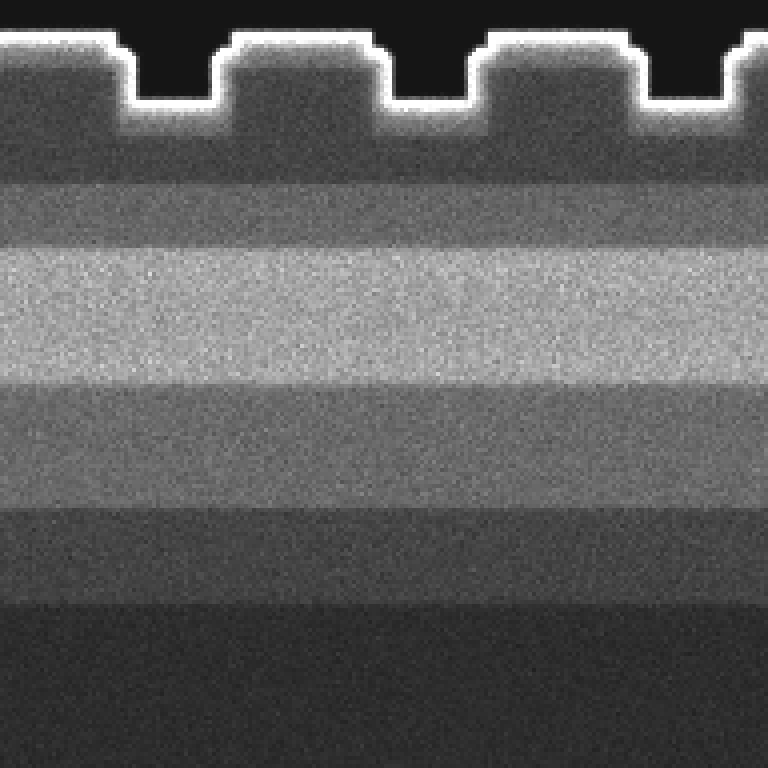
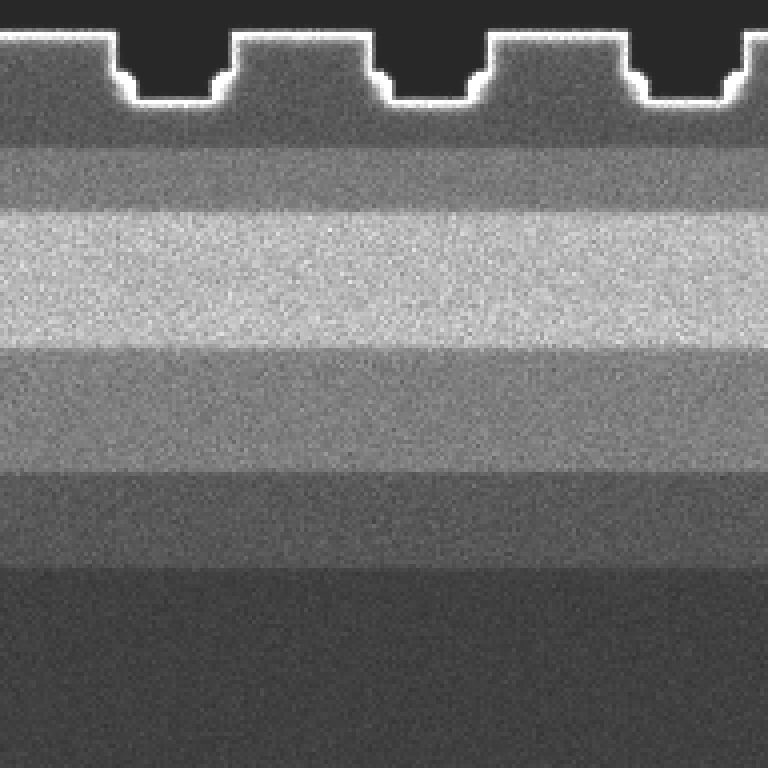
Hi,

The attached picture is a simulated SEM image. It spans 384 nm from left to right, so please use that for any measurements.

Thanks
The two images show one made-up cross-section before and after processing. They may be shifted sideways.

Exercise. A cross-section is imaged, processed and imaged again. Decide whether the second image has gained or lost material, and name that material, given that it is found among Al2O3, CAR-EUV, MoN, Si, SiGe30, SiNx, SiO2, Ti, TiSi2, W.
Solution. removed: SiO2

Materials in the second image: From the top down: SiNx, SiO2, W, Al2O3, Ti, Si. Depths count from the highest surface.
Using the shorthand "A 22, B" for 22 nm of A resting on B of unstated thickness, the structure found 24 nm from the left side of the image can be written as SiNx 58, SiO2 32, W 68, Al2O3 62, Ti 48, Si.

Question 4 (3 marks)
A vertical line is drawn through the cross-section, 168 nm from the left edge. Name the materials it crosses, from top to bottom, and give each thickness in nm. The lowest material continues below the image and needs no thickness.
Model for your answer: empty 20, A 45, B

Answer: SiNx 58, SiO2 32, W 68, Al2O3 62, Ti 48, Si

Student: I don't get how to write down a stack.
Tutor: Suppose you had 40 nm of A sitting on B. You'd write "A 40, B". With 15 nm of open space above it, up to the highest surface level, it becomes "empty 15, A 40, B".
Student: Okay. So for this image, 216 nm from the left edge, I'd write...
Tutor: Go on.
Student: empty 34, SiNx 24, SiO2 32, W 68, Al2O3 62, Ti 48, Si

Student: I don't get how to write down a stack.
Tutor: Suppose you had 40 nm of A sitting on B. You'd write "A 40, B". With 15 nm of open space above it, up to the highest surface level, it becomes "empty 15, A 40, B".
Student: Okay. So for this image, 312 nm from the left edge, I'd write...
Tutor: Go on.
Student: SiNx 58, SiO2 32, W 68, Al2O3 62, Ti 48, Si